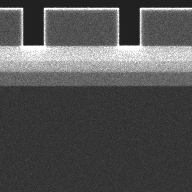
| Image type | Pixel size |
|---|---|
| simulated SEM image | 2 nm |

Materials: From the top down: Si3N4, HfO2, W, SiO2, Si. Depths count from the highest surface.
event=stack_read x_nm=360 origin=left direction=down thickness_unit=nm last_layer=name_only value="Si3N4 76, HfO2 30, W 22, SiO2 28, Si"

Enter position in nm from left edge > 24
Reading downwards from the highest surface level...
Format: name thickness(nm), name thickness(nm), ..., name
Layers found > Si3N4 76, HfO2 30, W 22, SiO2 28, Si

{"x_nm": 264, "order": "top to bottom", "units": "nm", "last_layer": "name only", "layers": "empty 76, HfO2 30, W 22, SiO2 28, Si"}